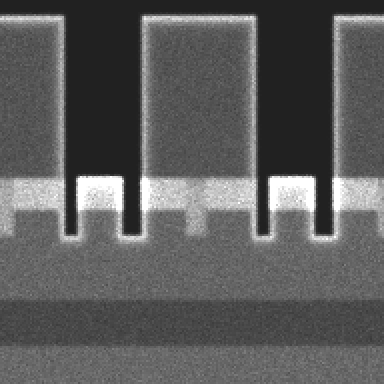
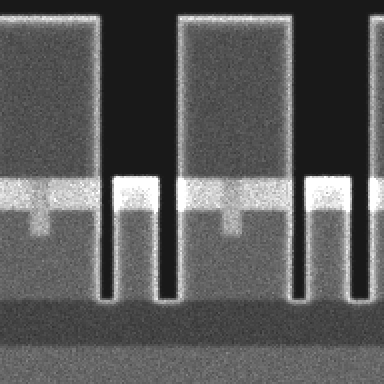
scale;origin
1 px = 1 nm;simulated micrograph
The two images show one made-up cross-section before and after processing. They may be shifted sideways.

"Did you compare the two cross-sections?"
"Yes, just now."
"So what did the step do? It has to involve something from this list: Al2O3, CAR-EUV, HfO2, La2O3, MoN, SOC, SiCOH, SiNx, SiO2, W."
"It removed SiO2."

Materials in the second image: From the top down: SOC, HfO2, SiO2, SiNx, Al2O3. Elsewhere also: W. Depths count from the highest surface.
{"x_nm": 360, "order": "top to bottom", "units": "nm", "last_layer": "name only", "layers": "empty 284, SiNx 46, Al2O3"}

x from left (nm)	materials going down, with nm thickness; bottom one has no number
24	SOC 162, HfO2 32, SiO2 90, SiNx 46, Al2O3